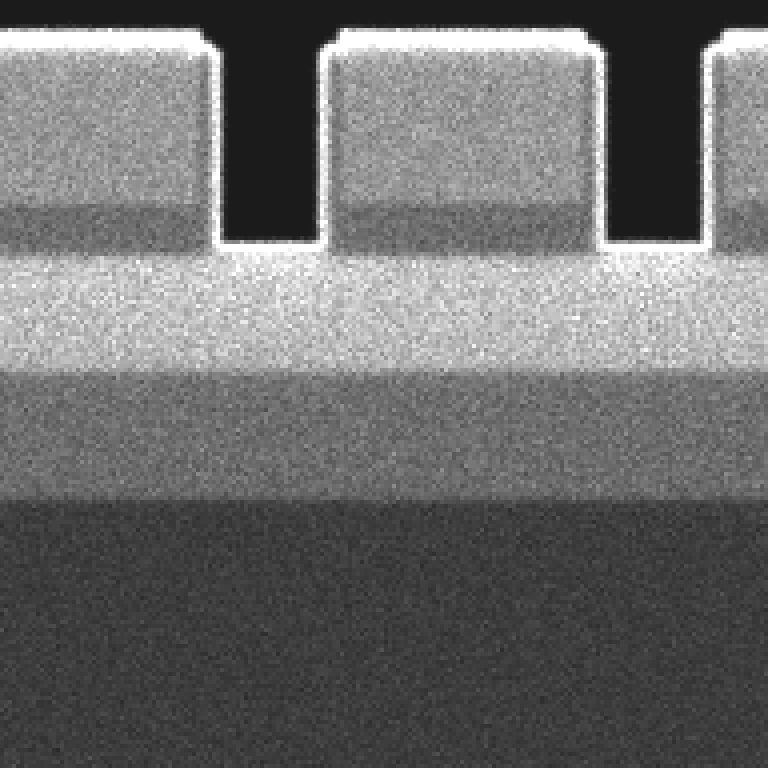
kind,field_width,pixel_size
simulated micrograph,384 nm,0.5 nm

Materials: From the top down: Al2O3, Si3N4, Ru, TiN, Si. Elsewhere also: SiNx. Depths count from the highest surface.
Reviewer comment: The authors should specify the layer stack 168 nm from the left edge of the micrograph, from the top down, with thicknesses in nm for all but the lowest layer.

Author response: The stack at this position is empty 6, SiNx 100, Si3N4 6, Ru 58, TiN 64, Si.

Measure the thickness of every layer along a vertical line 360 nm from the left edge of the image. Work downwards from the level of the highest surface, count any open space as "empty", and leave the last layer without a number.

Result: empty 6, SiNx 100, Si3N4 6, Ru 58, TiN 64, Si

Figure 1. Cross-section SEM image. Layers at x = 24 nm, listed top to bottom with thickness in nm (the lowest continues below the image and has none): Al2O3 86, Si3N4 26, Ru 58, TiN 64, Si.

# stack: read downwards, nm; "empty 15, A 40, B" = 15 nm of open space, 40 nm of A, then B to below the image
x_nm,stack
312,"empty 106, Si3N4 6, Ru 58, TiN 64, Si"